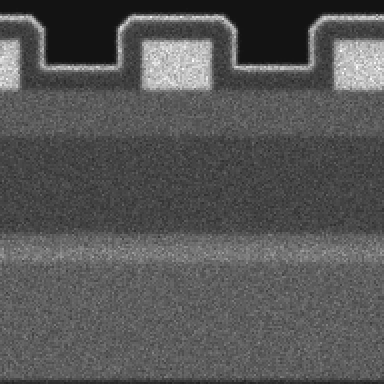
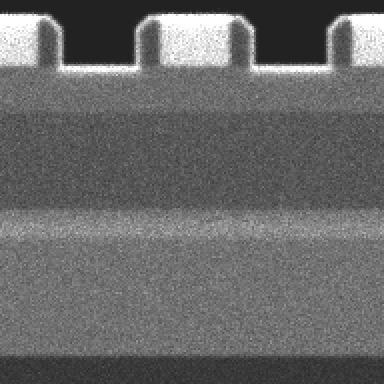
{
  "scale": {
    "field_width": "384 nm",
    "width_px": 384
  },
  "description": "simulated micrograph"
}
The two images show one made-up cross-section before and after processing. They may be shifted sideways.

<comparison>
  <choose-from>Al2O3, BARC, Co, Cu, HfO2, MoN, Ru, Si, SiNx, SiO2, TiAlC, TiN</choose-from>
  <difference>SiNx removed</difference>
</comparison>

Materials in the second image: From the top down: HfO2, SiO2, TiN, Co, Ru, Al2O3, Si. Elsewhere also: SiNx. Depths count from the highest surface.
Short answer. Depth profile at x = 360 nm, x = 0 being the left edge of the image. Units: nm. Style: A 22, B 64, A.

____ HfO2 50, SiO2 46, TiN 98, Co 12, Ru 16, Al2O3 118, Si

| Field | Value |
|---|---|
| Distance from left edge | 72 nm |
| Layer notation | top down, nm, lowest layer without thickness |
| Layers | empty 50, SiO2 46, TiN 98, Co 12, Ru 16, Al2O3 118, Si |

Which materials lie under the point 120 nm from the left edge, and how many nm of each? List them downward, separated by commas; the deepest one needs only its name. empty 50, SiO2 46, TiN 98, Co 12, Ru 16, Al2O3 118, Si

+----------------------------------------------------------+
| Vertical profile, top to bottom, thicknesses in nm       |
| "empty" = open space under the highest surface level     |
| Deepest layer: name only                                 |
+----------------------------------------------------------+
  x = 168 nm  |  HfO2 50, SiO2 46, TiN 98, Co 12, Ru 16, Al2O3 118, Si